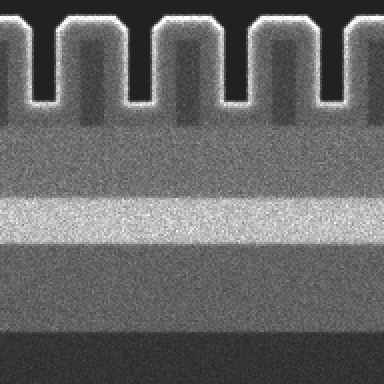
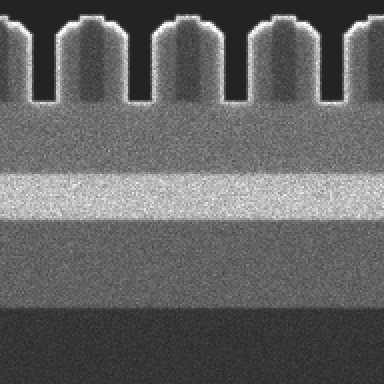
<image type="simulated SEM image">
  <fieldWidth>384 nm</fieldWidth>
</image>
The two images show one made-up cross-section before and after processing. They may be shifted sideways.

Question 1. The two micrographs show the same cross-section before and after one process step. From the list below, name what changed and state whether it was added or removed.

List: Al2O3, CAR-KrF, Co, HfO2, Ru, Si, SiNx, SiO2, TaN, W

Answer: SiO2, removed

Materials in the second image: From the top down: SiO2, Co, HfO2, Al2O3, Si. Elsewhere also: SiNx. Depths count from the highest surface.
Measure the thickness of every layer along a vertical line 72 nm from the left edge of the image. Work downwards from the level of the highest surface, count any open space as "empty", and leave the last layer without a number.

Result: empty 6, SiO2 80, Co 72, HfO2 46, Al2O3 88, Si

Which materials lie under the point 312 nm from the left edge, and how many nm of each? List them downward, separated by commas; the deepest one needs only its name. empty 12, SiO2 74, Co 72, HfO2 46, Al2O3 88, Si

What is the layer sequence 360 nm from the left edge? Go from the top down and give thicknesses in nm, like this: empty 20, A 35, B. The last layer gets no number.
empty 6, SiO2 80, Co 72, HfO2 46, Al2O3 88, Si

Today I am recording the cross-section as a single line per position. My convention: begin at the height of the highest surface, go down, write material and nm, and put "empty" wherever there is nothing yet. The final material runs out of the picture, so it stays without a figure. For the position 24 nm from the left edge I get empty 12, SiO2 74, Co 72, HfO2 46, Al2O3 88, Si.